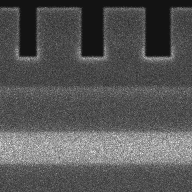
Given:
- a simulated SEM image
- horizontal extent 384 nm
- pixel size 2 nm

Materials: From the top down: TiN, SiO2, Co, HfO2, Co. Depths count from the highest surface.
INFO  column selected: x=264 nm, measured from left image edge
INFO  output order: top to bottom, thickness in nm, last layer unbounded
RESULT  TiN 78, SiO2 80, Co 90, HfO2 64, Co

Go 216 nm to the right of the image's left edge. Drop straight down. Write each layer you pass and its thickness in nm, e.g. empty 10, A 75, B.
TiN 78, SiO2 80, Co 90, HfO2 64, Co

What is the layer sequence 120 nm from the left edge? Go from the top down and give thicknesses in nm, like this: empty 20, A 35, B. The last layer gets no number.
TiN 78, SiO2 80, Co 90, HfO2 64, Co